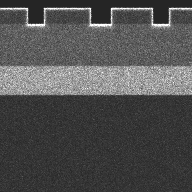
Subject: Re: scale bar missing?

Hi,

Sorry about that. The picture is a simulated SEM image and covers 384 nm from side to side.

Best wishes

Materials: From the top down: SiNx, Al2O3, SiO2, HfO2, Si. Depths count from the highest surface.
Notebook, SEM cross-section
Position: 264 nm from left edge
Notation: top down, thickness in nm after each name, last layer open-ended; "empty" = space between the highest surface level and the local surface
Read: SiNx 32, Al2O3 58, SiO2 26, HfO2 58, Si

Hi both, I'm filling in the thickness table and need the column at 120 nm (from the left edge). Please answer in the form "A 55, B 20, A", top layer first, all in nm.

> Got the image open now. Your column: SiNx 32, Al2O3 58, SiO2 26, HfO2 58, Si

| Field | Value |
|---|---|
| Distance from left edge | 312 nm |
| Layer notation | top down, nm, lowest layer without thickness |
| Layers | empty 32, Al2O3 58, SiO2 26, HfO2 58, Si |